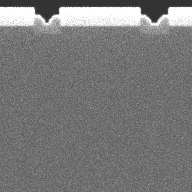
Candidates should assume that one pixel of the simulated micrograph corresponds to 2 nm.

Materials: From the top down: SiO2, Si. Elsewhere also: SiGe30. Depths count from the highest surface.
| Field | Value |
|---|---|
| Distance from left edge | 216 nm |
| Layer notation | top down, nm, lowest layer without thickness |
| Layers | SiO2 36, Si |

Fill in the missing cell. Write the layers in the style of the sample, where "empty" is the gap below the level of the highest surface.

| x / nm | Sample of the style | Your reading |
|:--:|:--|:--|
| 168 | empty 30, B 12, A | SiO2 36, Si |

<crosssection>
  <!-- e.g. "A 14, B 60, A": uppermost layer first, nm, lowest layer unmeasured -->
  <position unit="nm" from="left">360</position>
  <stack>SiO2 36, Si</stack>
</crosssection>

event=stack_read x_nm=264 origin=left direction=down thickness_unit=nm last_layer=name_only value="SiO2 36, Si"